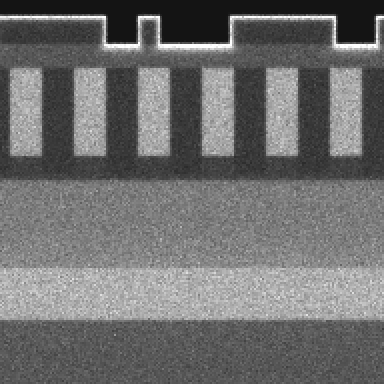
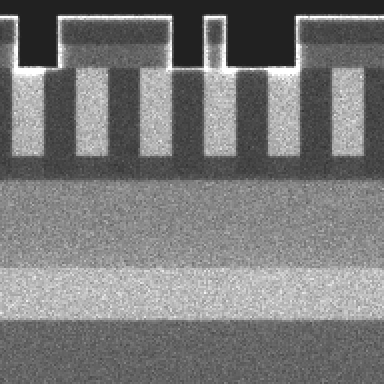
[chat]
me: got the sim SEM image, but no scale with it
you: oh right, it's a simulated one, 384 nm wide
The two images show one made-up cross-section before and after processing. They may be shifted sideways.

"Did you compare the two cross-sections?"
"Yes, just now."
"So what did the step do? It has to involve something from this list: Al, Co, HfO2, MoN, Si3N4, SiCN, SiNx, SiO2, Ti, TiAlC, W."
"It removed SiO2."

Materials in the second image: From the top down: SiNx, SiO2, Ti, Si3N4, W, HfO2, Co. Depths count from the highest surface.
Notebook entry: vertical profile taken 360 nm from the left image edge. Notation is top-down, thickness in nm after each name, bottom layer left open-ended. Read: SiNx 28, SiO2 24, HfO2 88, Si3N4 24, W 88, HfO2 52, Co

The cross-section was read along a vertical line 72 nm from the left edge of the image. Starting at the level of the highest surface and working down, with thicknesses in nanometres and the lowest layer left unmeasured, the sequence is SiNx 28, SiO2 24, Ti 106, Si3N4 6, W 88, HfO2 52, Co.